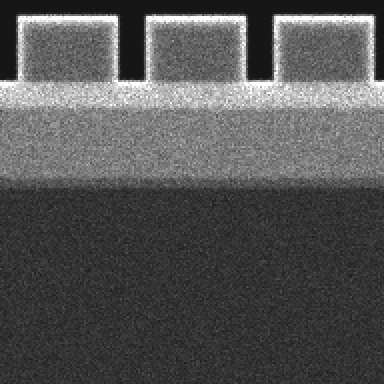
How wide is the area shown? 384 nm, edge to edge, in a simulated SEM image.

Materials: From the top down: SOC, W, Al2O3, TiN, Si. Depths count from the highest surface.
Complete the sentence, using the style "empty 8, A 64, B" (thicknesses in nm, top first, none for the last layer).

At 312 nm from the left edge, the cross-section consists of SOC 66, W 26, Al2O3 70, TiN 10, Si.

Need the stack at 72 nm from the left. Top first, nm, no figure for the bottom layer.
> SOC 66, W 26, Al2O3 70, TiN 10, Si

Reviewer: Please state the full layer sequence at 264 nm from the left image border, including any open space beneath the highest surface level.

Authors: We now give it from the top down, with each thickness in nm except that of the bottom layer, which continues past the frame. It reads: empty 66, W 26, Al2O3 70, TiN 10, Si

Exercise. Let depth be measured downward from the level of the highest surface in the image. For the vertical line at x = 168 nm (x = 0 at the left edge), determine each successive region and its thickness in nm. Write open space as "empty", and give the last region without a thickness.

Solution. SOC 66, W 26, Al2O3 70, TiN 10, Si